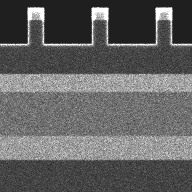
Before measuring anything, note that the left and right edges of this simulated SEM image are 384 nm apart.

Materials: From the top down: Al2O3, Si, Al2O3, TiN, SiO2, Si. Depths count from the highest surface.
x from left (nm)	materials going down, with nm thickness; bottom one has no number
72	Al2O3 24, Si 108, Al2O3 36, TiN 88, SiO2 48, Si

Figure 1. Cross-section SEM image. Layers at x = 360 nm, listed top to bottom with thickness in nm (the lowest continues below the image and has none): empty 72, Si 60, Al2O3 36, TiN 88, SiO2 48, Si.